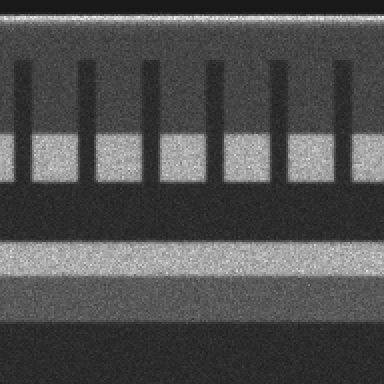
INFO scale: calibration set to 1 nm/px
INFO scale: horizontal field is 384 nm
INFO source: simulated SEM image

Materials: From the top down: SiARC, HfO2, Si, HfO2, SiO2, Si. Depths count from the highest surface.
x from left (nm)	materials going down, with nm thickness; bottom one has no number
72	SiARC 118, HfO2 48, Si 60, HfO2 34, SiO2 46, Si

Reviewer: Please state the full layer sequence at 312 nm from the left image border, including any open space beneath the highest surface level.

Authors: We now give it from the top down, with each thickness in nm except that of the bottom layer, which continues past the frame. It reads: SiARC 118, HfO2 48, Si 60, HfO2 34, SiO2 46, Si